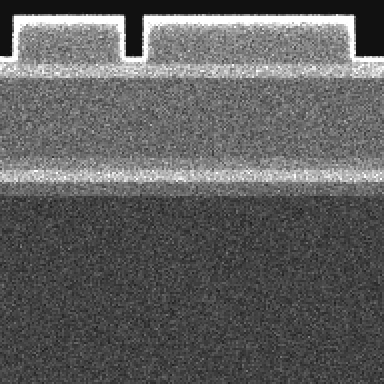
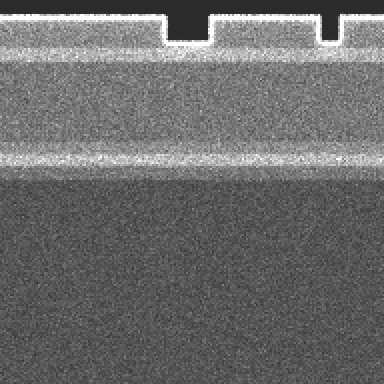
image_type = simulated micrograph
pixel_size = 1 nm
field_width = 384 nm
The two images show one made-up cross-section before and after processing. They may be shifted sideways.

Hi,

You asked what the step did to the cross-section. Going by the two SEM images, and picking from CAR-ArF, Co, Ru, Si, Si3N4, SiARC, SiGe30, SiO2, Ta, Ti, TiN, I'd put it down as SiARC, removed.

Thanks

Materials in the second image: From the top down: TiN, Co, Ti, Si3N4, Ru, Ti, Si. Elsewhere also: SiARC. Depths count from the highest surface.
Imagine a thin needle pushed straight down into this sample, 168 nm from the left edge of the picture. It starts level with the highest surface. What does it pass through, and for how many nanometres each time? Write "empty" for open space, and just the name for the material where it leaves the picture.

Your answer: empty 26, TiN 6, Co 14, Ti 80, Si3N4 12, Ru 12, Ti 14, Si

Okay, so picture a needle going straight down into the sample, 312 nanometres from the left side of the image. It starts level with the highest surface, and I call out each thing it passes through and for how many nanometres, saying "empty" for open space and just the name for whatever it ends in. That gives TiN 32, Co 14, Ti 80, Si3N4 12, Ru 12, Ti 14, Si